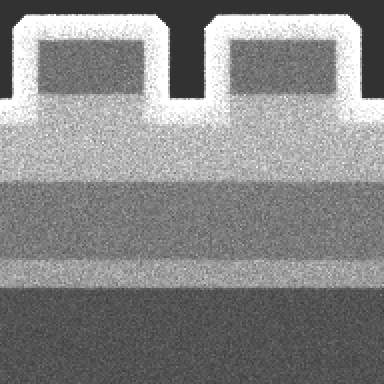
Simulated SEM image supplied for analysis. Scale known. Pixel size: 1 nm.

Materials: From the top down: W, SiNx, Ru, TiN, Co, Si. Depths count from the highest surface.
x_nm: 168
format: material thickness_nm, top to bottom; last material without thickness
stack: empty 84, W 24, Ru 58, TiN 78, Co 28, Si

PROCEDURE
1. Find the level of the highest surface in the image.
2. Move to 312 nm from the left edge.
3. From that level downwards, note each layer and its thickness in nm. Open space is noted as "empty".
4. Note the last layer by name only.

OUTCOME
W 24, SiNx 54, Ru 88, TiN 78, Co 28, Si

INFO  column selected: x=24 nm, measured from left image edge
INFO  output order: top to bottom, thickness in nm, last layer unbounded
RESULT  empty 2, W 106, Ru 58, TiN 78, Co 28, Si